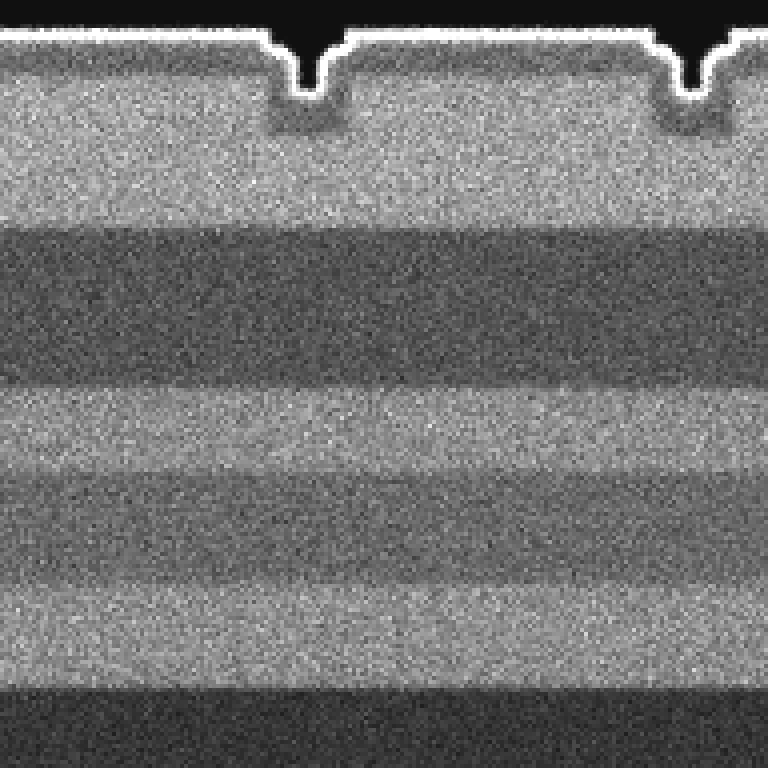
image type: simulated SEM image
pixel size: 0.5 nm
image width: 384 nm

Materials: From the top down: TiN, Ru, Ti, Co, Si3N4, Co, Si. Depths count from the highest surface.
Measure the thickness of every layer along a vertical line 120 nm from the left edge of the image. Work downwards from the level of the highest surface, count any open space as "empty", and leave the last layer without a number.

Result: TiN 22, Ru 76, Ti 80, Co 42, Si3N4 56, Co 52, Si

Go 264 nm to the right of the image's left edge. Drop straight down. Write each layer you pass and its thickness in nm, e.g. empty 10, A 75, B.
TiN 22, Ru 76, Ti 80, Co 42, Si3N4 56, Co 52, Si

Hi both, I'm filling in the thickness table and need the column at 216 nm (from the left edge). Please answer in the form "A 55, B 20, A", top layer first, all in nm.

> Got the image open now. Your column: TiN 22, Ru 76, Ti 80, Co 42, Si3N4 56, Co 52, Si